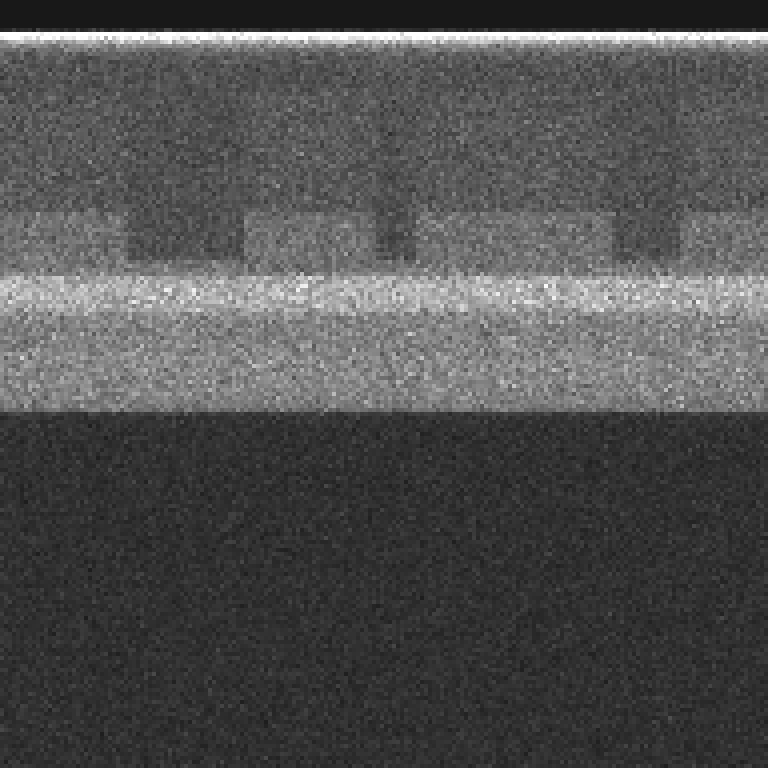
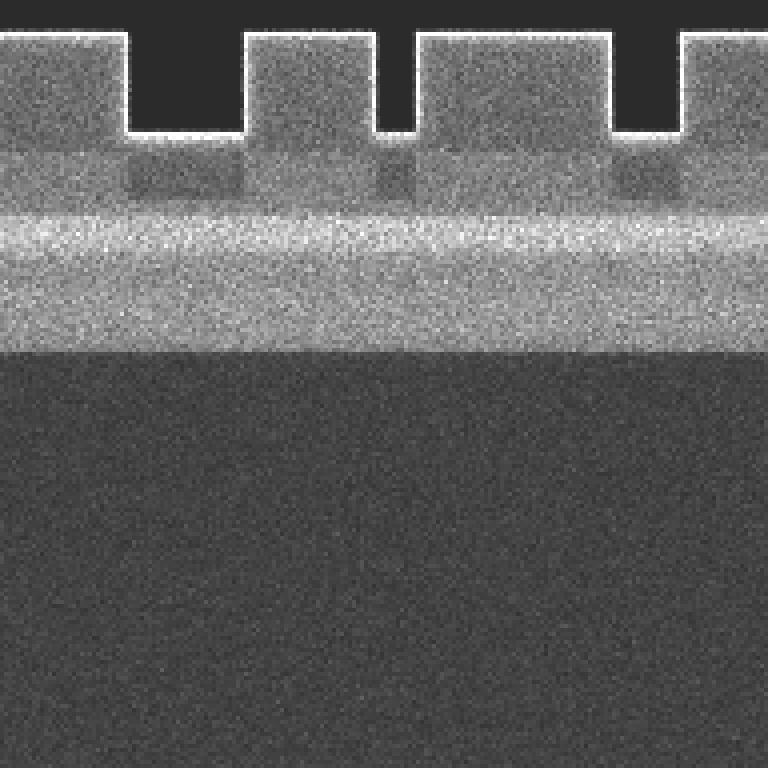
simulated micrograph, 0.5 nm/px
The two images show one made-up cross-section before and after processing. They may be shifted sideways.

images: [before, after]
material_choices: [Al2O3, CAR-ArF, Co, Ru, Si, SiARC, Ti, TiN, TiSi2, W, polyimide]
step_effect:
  removed: SiARC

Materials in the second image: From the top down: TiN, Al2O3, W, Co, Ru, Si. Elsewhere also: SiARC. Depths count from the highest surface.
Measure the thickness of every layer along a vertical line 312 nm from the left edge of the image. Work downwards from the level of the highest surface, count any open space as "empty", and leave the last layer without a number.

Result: empty 50, SiARC 34, Al2O3 8, W 18, Co 20, Ru 30, Si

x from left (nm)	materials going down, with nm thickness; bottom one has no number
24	TiN 60, Al2O3 32, W 18, Co 20, Ru 30, Si